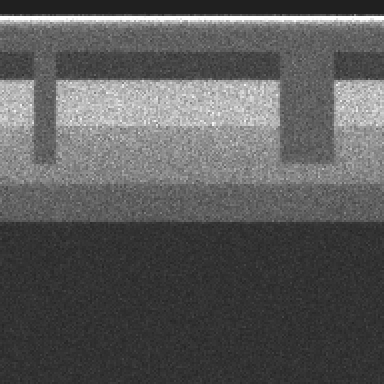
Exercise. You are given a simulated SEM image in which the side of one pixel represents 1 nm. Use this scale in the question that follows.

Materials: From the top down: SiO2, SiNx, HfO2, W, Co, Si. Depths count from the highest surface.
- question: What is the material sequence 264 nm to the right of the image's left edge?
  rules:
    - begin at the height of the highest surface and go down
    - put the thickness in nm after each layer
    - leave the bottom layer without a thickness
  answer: SiO2 36, SiNx 28, HfO2 46, W 58, Co 38, Si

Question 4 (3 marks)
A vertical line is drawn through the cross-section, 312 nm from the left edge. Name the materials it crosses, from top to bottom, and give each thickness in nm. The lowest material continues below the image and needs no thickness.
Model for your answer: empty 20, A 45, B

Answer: SiO2 148, W 20, Co 38, Si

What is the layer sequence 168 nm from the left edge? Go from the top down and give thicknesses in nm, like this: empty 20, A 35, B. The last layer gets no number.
SiO2 36, SiNx 28, HfO2 46, W 58, Co 38, Si